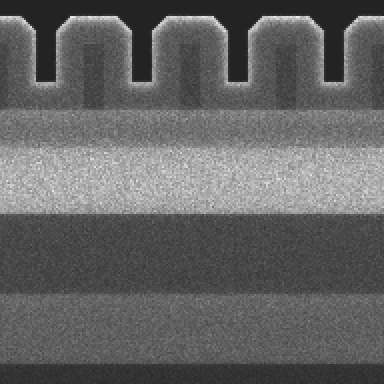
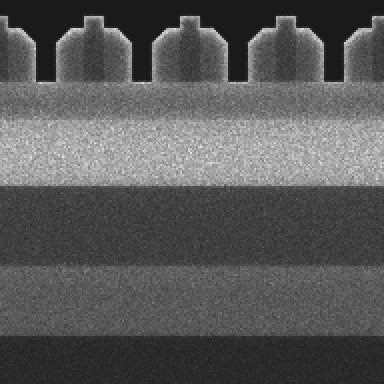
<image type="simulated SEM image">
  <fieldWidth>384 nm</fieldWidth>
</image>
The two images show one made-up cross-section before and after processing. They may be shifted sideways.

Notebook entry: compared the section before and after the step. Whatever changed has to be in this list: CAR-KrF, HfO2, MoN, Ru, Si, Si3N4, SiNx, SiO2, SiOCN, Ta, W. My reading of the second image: SiO2 removed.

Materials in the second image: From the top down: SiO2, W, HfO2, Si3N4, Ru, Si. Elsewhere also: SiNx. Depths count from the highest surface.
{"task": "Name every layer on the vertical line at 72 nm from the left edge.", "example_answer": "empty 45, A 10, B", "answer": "empty 12, SiO2 54, W 38, HfO2 66, Si3N4 80, Ru 70, Si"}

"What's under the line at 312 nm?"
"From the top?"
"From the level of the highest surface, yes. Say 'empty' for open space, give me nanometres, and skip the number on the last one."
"empty 16, SiO2 50, W 38, HfO2 66, Si3N4 80, Ru 70, Si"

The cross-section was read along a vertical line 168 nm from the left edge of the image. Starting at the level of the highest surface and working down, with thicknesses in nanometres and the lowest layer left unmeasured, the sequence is empty 12, SiO2 54, W 38, HfO2 66, Si3N4 80, Ru 70, Si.